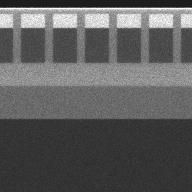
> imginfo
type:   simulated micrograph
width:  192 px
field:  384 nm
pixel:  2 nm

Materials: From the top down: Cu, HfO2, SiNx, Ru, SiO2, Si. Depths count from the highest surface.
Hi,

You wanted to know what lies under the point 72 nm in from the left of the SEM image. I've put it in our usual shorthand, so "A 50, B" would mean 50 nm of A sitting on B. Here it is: Cu 12, HfO2 28, SiNx 70, Ru 46, SiO2 66, Si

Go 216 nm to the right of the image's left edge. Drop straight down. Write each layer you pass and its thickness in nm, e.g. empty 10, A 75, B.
Cu 12, HfO2 28, SiNx 70, Ru 46, SiO2 66, Si